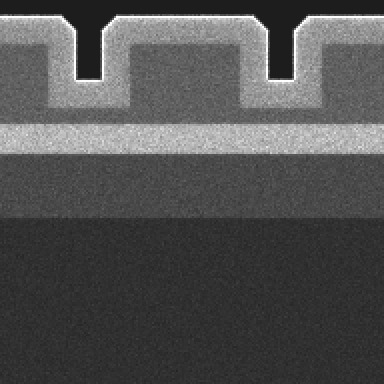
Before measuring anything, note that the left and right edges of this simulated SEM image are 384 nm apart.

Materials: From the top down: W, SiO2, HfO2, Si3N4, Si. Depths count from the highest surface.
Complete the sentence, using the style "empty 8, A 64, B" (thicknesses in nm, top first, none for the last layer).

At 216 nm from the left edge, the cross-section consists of W 28, SiO2 80, HfO2 30, Si3N4 64, Si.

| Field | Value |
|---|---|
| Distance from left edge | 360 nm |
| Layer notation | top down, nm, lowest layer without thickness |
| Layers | W 28, SiO2 80, HfO2 30, Si3N4 64, Si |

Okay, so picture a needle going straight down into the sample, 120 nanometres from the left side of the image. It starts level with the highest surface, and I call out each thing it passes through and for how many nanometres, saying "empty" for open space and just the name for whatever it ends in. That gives W 92, SiO2 16, HfO2 30, Si3N4 64, Si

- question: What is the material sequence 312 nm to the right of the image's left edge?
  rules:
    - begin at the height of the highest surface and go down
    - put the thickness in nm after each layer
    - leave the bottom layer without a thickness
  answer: W 92, SiO2 16, HfO2 30, Si3N4 64, Si